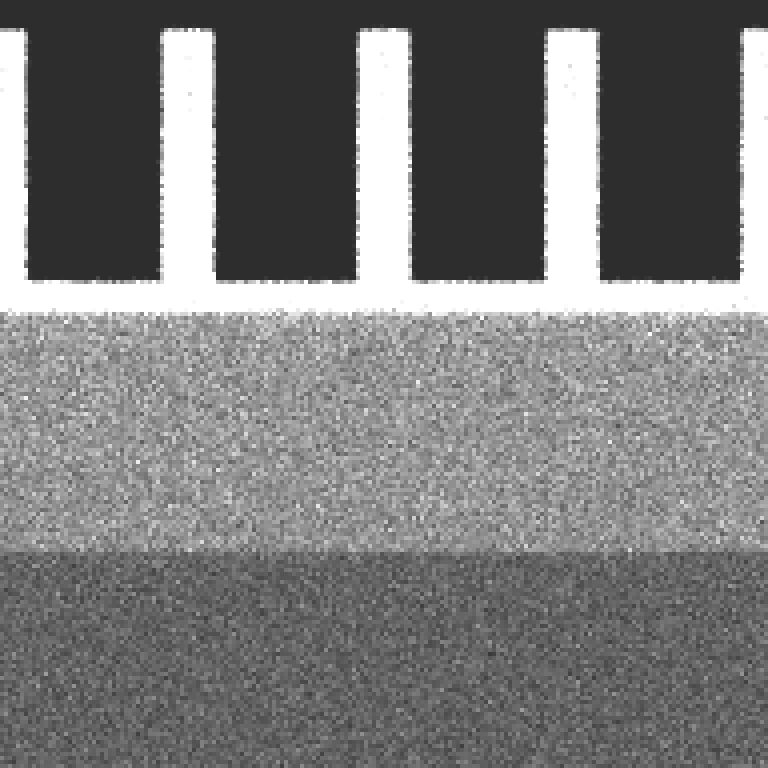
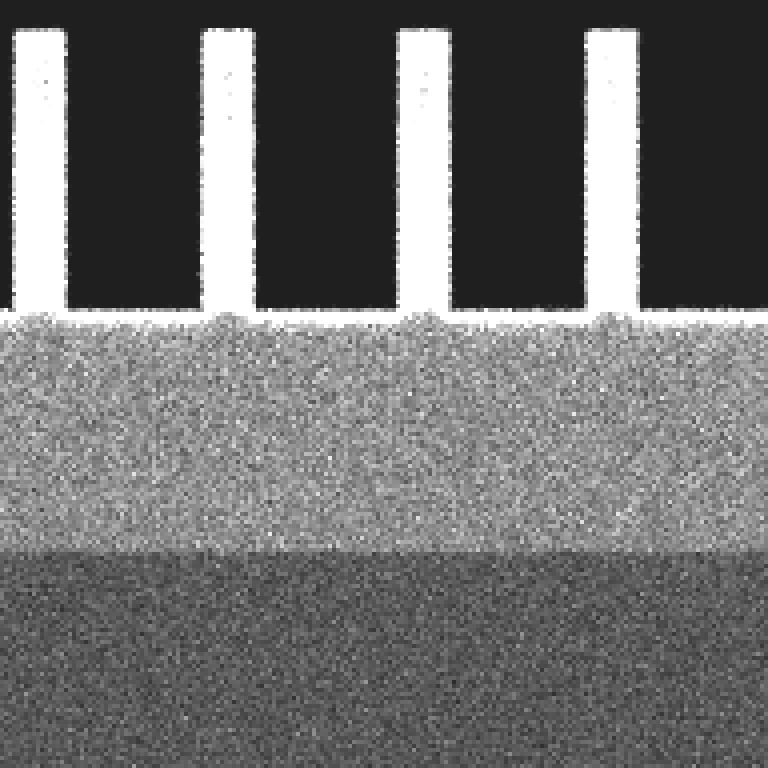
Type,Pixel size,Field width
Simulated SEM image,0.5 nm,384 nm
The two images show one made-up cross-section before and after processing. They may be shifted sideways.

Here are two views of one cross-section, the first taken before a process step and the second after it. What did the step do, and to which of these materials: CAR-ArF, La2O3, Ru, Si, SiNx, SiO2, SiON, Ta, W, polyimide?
It removed Ru.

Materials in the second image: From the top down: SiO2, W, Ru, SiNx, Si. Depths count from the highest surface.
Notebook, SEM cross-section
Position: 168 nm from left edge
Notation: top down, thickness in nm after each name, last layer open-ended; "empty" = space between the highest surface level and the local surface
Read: empty 140, SiNx 120, Si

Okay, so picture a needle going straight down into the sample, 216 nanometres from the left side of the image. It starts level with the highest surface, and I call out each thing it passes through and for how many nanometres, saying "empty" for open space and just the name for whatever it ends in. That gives SiO2 48, W 78, Ru 14, SiNx 120, Si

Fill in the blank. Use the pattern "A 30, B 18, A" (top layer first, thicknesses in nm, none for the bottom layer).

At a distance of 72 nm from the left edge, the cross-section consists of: empty 140, SiNx 120, Si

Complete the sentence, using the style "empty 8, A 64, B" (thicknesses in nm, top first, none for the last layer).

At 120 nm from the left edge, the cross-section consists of SiO2 48, W 78, Ru 14, SiNx 120, Si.